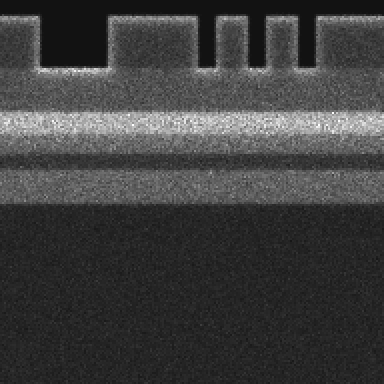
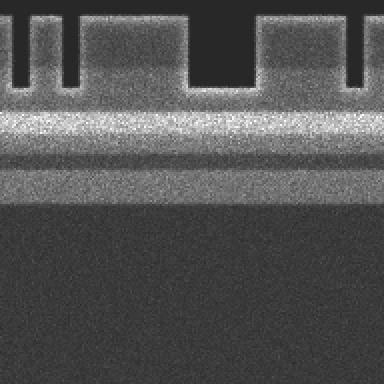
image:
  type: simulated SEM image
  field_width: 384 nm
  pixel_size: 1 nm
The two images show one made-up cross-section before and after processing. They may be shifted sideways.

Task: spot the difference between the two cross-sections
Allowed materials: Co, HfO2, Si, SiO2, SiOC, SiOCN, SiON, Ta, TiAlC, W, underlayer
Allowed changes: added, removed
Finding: removed SiO2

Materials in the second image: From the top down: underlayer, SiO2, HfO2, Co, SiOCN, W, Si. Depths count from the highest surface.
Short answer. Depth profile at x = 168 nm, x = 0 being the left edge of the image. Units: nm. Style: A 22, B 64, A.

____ underlayer 52, SiO2 44, HfO2 22, Co 20, SiOCN 16, W 34, Si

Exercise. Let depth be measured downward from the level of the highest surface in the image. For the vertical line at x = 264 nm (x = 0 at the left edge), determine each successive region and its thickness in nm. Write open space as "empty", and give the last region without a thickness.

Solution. underlayer 52, SiO2 44, HfO2 22, Co 20, SiOCN 16, W 34, Si